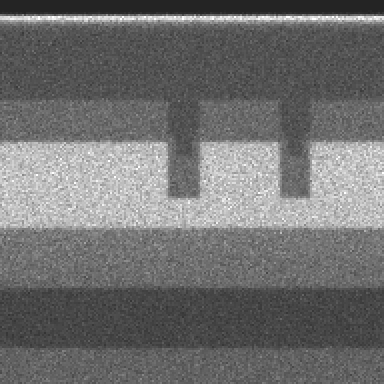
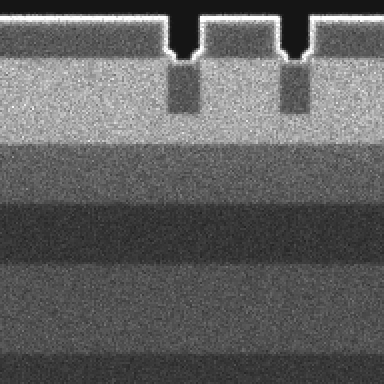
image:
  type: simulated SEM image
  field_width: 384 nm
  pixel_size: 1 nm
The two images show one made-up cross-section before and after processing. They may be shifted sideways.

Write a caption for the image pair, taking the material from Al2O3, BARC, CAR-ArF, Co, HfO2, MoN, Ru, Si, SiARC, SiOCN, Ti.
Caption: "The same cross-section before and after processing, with SiARC removed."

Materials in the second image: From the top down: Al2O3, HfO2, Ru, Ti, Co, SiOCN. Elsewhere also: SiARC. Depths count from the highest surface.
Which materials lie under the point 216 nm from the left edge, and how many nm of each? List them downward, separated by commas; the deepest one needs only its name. Al2O3 42, HfO2 86, Ru 60, Ti 60, Co 90, SiOCN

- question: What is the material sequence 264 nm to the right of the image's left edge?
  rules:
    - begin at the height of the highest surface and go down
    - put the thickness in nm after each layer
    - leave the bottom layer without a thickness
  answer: Al2O3 42, HfO2 86, Ru 60, Ti 60, Co 90, SiOCN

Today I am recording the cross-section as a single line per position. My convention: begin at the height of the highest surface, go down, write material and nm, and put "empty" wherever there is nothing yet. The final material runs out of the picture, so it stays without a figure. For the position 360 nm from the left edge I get Al2O3 42, HfO2 86, Ru 60, Ti 60, Co 90, SiOCN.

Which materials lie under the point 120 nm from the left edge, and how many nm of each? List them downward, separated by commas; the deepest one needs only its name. Al2O3 42, HfO2 86, Ru 60, Ti 60, Co 90, SiOCN